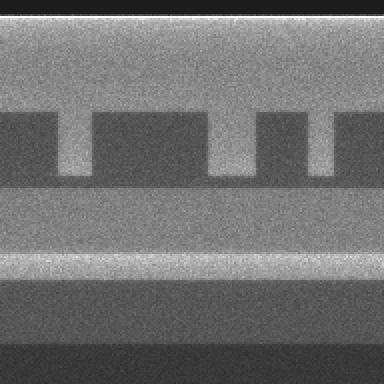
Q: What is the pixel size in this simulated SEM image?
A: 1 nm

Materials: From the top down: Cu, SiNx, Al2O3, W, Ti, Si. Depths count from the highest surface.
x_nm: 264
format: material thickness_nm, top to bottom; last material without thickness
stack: Cu 96, SiNx 76, Al2O3 66, W 26, Ti 64, Si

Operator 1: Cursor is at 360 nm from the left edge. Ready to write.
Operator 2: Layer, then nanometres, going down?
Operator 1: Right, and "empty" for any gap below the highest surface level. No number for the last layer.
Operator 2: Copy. Cu 96, SiNx 76, Al2O3 66, W 26, Ti 64, Si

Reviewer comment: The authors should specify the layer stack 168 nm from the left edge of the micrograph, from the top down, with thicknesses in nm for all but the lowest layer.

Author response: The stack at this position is Cu 96, SiNx 76, Al2O3 66, W 26, Ti 64, Si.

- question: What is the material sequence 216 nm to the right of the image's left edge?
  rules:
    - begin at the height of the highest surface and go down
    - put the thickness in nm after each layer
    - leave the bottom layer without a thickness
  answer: Cu 160, SiNx 12, Al2O3 66, W 26, Ti 64, Si